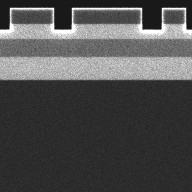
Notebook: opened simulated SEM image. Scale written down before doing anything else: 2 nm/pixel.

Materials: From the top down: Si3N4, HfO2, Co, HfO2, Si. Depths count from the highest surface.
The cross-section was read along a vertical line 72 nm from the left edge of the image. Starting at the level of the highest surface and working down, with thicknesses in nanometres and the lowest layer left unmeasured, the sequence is Si3N4 32, HfO2 30, Co 36, HfO2 46, Si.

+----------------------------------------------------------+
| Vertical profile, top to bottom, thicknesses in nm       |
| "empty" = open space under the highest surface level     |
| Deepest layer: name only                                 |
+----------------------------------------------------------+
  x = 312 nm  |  empty 44, HfO2 18, Co 36, HfO2 46, Si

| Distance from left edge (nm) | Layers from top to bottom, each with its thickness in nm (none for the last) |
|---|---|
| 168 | Si3N4 32, HfO2 30, Co 36, HfO2 46, Si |